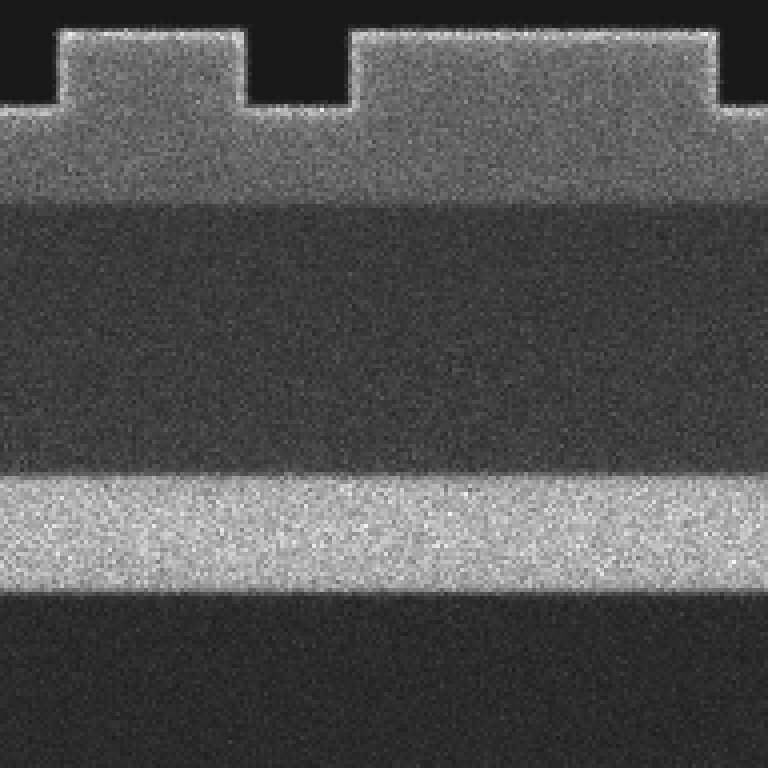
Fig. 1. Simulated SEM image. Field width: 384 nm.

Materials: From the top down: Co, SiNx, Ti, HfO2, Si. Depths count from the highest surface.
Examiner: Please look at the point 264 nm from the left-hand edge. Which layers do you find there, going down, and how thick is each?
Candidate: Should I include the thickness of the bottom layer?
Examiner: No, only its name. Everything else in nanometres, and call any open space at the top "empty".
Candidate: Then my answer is Co 86, SiNx 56, Ti 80, HfO2 58, Si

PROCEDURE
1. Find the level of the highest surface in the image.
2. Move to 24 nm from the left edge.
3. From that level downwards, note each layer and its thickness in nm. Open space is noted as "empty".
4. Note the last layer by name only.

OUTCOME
empty 38, Co 48, SiNx 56, Ti 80, HfO2 58, Si